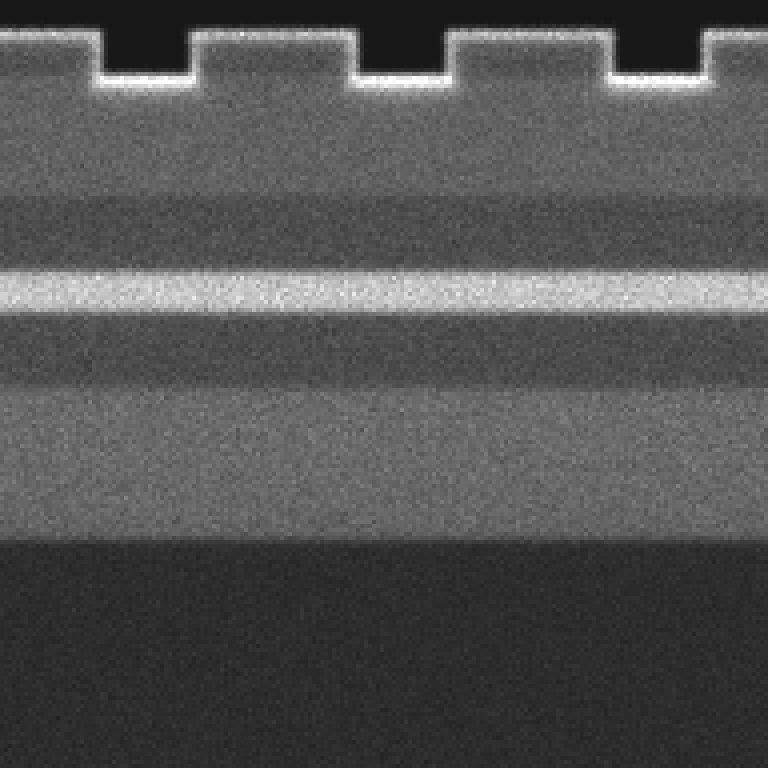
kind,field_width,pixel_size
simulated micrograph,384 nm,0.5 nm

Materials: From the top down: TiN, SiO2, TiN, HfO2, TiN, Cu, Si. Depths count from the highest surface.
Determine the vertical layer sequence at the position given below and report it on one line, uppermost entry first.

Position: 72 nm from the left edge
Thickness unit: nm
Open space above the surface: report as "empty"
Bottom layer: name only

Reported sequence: empty 22, SiO2 60, TiN 38, HfO2 20, TiN 38, Cu 76, Si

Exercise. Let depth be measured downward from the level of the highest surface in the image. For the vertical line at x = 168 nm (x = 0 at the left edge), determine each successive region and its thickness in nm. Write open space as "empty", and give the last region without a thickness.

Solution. TiN 22, SiO2 60, TiN 38, HfO2 20, TiN 38, Cu 76, Si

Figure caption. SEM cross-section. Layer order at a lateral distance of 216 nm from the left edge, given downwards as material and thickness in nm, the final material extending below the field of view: empty 22, SiO2 60, TiN 38, HfO2 20, TiN 38, Cu 76, Si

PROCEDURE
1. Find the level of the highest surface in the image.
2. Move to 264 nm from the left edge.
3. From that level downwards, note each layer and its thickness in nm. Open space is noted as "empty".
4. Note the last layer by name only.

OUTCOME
TiN 22, SiO2 60, TiN 38, HfO2 20, TiN 38, Cu 76, Si